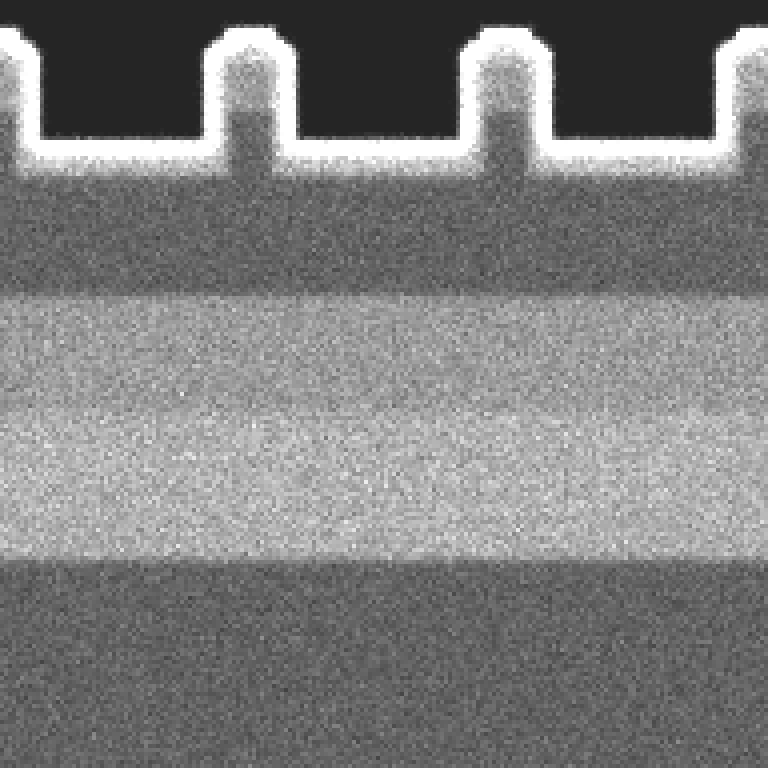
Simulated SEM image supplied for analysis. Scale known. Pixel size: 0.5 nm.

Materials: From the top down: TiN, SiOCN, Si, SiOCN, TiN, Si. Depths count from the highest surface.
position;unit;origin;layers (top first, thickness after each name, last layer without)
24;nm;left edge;empty 56, TiN 16, Si 60, SiOCN 58, TiN 74, Si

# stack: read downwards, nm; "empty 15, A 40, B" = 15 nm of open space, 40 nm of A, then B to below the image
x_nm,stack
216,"empty 56, TiN 16, Si 60, SiOCN 58, TiN 74, Si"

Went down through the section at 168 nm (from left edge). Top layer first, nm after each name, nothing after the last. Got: empty 56, TiN 16, Si 60, SiOCN 58, TiN 74, Si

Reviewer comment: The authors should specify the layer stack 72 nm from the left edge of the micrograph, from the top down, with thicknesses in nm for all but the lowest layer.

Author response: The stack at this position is empty 56, TiN 16, Si 60, SiOCN 58, TiN 74, Si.